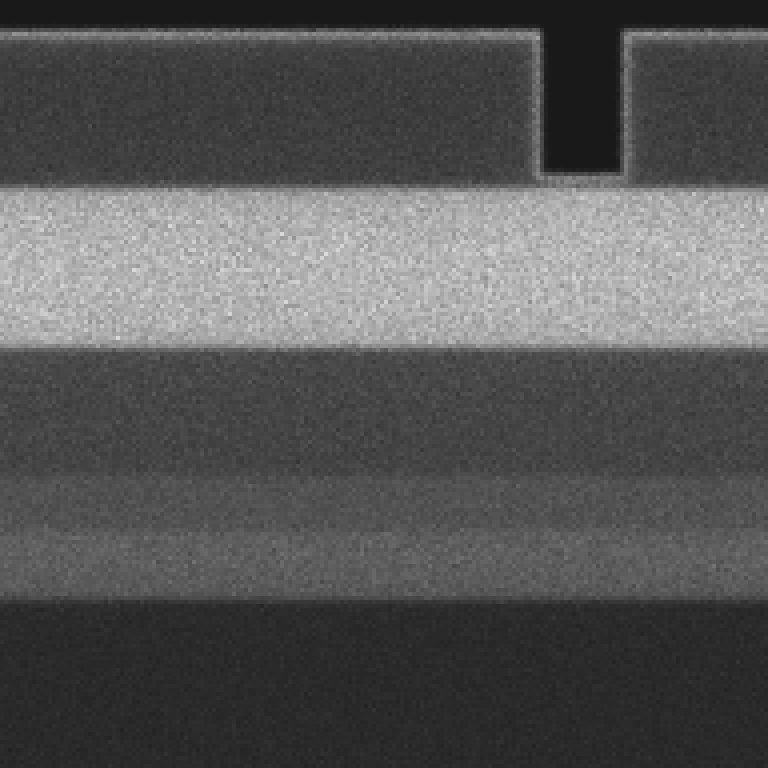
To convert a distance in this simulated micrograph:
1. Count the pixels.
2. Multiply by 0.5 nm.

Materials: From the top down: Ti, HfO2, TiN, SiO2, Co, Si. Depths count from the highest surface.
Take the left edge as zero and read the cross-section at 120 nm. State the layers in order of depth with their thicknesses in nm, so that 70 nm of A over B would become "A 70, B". Ti 78, HfO2 80, TiN 64, SiO2 28, Co 34, Si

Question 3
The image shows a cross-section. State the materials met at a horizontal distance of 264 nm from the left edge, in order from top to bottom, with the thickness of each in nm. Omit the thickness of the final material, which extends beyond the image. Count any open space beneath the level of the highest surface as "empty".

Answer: Ti 78, HfO2 80, TiN 64, SiO2 28, Co 34, Si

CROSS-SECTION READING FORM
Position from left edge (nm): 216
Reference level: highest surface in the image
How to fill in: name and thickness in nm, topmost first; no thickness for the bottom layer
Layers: Ti 78, HfO2 80, TiN 64, SiO2 28, Co 34, Si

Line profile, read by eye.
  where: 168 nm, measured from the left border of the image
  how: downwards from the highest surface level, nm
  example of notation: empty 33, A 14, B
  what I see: Ti 78, HfO2 80, TiN 64, SiO2 28, Co 34, Si